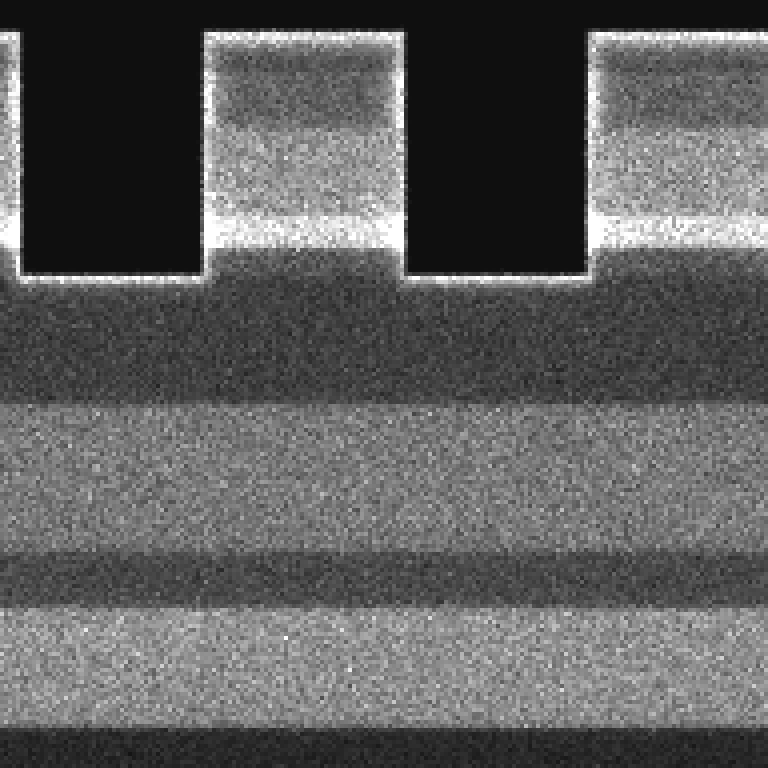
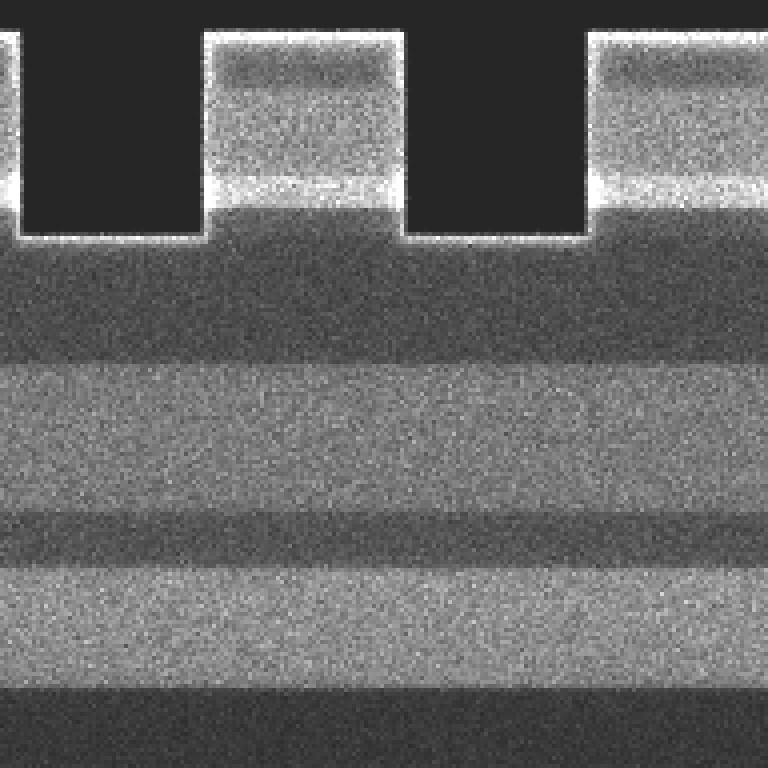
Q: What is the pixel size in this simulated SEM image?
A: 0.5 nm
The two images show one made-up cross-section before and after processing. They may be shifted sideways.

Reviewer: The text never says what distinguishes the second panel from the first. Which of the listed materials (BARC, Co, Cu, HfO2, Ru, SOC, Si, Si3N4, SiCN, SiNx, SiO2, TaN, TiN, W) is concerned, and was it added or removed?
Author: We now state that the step removed SOC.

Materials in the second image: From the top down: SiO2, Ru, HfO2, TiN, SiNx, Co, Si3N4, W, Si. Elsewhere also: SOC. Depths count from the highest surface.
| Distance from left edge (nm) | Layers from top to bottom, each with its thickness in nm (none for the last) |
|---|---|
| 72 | empty 102, SiNx 64, Co 74, Si3N4 28, W 60, Si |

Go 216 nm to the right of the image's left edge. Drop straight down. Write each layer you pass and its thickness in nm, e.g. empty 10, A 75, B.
empty 102, SiNx 64, Co 74, Si3N4 28, W 60, Si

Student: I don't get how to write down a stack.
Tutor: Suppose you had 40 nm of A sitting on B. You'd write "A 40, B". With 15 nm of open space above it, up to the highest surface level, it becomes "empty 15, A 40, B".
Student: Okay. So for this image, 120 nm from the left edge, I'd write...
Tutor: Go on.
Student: SiO2 28, Ru 44, HfO2 16, TiN 14, SiNx 64, Co 74, Si3N4 28, W 60, Si